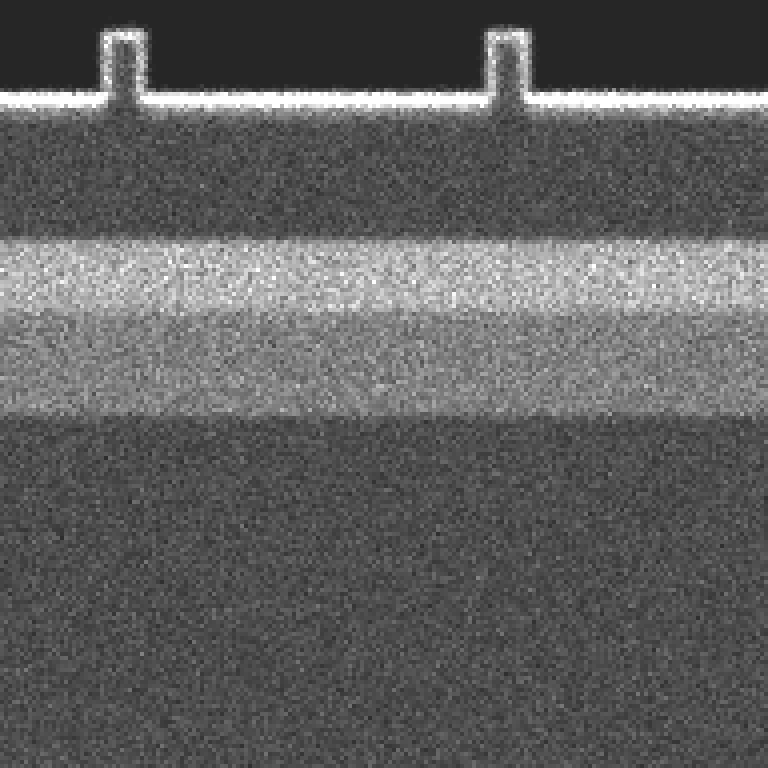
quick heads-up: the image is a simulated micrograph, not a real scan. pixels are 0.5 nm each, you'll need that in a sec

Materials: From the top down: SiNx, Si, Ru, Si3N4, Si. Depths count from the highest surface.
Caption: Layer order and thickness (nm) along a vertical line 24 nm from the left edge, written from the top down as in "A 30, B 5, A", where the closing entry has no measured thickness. empty 32, SiNx 12, Si 60, Ru 36, Si3N4 52, Si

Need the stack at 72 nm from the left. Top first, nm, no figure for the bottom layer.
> empty 32, SiNx 12, Si 60, Ru 36, Si3N4 52, Si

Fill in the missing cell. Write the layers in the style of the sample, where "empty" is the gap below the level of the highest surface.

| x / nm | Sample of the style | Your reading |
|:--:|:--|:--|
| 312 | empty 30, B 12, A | empty 32, SiNx 12, Si 60, Ru 36, Si3N4 52, Si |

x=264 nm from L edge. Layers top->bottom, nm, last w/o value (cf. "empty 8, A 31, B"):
empty 32, SiNx 12, Si 60, Ru 36, Si3N4 52, Si